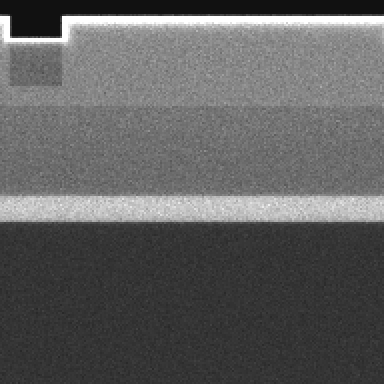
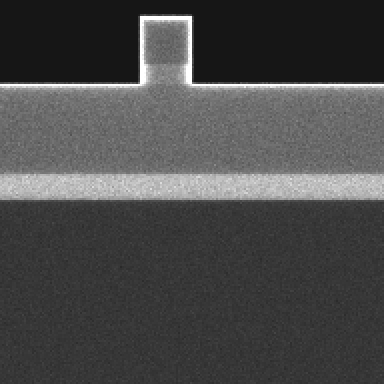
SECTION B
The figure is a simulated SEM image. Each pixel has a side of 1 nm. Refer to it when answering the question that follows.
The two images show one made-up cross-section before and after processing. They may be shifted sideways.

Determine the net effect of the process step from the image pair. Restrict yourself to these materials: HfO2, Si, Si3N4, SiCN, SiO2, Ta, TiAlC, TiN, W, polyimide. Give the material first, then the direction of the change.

SiO2: removed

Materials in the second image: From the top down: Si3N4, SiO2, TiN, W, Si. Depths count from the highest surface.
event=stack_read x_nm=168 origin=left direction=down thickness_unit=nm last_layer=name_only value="Si3N4 48, SiO2 20, TiN 90, W 26, Si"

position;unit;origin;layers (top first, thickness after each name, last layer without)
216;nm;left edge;empty 68, TiN 90, W 26, Si